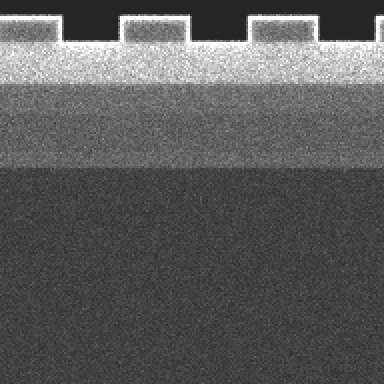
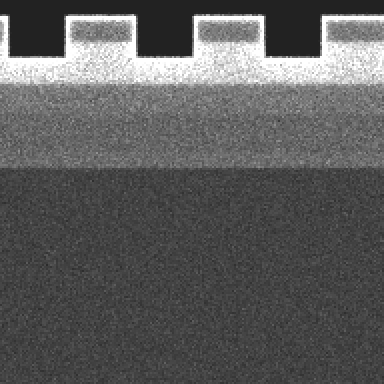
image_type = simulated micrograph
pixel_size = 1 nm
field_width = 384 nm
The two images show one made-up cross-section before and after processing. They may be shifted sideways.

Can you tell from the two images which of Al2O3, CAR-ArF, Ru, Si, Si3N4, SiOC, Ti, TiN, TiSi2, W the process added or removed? Yes, it removed W.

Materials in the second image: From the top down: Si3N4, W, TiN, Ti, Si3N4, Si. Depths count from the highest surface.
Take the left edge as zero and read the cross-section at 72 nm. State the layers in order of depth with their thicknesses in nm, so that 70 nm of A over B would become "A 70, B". Si3N4 26, W 42, TiN 30, Ti 38, Si3N4 16, Si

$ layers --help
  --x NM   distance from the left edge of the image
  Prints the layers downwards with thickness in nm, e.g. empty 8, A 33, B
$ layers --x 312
empty 42, W 26, TiN 30, Ti 38, Si3N4 16, Si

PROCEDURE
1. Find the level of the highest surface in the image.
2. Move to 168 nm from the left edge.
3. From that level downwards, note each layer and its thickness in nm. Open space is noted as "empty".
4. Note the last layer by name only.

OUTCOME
empty 42, W 26, TiN 30, Ti 38, Si3N4 16, Si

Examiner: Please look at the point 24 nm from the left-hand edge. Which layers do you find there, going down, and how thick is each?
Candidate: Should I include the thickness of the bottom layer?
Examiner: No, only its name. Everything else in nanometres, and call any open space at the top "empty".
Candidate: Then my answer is empty 42, W 26, TiN 30, Ti 38, Si3N4 16, Si